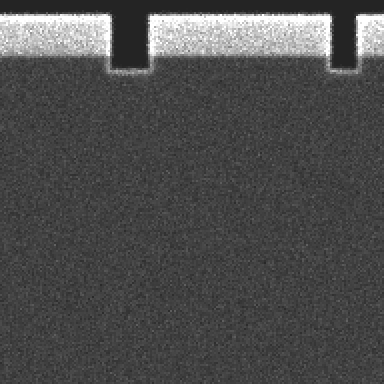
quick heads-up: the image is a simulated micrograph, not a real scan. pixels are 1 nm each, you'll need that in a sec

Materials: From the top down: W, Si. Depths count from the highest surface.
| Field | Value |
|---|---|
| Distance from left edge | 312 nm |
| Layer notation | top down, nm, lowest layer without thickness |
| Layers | W 40, Si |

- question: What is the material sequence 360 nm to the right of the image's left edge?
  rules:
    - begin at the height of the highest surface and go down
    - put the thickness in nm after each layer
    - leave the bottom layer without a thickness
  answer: W 40, Si